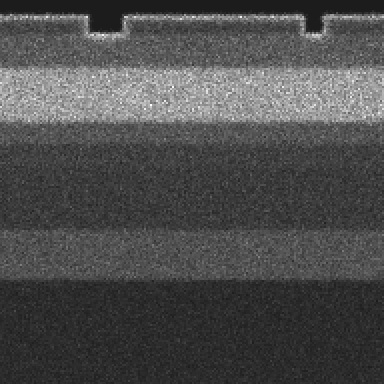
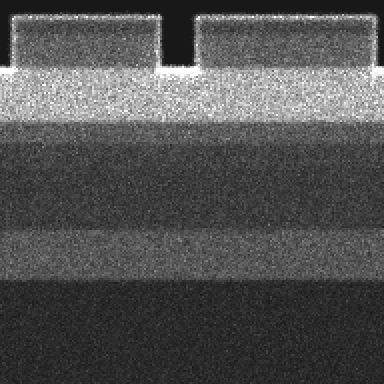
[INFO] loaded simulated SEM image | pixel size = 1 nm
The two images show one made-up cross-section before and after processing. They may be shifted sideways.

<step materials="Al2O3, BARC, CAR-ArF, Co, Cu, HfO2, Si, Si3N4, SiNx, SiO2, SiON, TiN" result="removed Co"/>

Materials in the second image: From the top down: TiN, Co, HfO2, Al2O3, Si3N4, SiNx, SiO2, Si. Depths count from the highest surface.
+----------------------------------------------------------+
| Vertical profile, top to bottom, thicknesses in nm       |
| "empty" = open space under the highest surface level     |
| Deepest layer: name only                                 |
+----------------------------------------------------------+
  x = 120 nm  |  TiN 18, Co 34, HfO2 54, Al2O3 22, Si3N4 24, SiNx 62, SiO2 50, Si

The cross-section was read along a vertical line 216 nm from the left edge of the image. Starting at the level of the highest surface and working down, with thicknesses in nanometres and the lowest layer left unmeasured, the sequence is TiN 18, Co 34, HfO2 54, Al2O3 22, Si3N4 24, SiNx 62, SiO2 50, Si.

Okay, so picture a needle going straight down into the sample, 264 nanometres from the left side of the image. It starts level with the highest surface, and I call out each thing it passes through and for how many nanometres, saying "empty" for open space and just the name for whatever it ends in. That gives TiN 18, Co 34, HfO2 54, Al2O3 22, Si3N4 24, SiNx 62, SiO2 50, Si